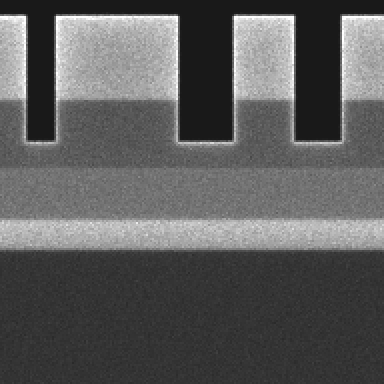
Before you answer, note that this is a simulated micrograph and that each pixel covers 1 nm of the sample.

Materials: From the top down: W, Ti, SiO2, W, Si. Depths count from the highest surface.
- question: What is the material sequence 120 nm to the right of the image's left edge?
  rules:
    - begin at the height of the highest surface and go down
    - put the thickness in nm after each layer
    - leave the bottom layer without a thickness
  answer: W 84, Ti 68, SiO2 52, W 30, Si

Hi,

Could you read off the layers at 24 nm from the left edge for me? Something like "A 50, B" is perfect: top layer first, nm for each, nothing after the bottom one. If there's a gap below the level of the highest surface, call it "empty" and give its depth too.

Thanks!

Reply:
W 84, Ti 68, SiO2 52, W 30, Si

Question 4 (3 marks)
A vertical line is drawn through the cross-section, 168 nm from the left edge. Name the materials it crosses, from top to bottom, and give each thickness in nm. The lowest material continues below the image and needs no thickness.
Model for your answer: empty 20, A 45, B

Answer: W 84, Ti 68, SiO2 52, W 30, Si